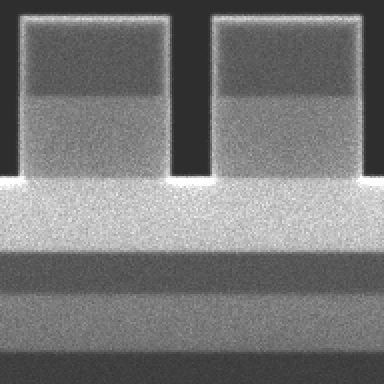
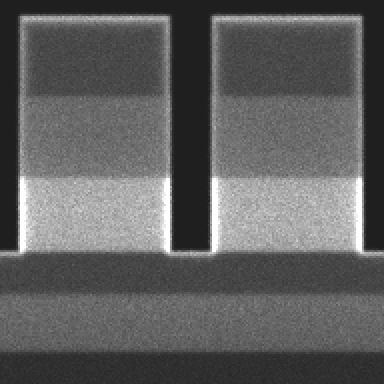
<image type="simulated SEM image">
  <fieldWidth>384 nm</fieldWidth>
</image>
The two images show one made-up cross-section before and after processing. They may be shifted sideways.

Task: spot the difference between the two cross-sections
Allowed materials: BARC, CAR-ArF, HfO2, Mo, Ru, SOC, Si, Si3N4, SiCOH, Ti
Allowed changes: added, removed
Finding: removed HfO2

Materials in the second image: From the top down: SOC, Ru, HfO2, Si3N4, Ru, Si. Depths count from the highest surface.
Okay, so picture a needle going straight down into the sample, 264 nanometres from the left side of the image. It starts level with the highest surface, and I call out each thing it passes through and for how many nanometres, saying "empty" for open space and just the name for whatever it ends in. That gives SOC 80, Ru 82, HfO2 74, Si3N4 42, Ru 58, Si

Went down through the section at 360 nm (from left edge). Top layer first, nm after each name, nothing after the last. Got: SOC 80, Ru 82, HfO2 74, Si3N4 42, Ru 58, Si